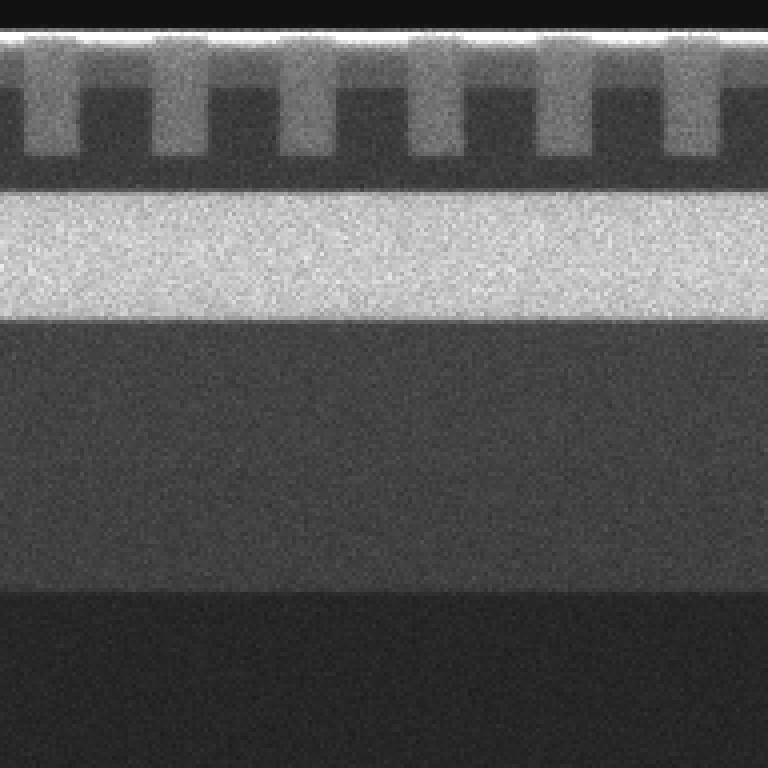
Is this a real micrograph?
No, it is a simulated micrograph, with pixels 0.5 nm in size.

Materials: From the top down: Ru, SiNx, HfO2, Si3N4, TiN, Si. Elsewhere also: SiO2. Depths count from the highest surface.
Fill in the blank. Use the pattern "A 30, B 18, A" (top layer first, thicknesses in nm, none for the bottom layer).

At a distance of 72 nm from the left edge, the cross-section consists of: SiO2 28, SiNx 52, HfO2 64, Si3N4 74, TiN 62, Si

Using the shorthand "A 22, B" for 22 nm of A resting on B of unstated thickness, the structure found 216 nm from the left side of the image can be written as Ru 62, SiNx 18, HfO2 64, Si3N4 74, TiN 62, Si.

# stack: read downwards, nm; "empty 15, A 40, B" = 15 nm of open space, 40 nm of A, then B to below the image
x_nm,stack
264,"SiO2 28, SiNx 52, HfO2 64, Si3N4 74, TiN 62, Si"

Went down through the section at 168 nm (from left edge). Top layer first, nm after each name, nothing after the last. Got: SiO2 28, SiNx 52, HfO2 64, Si3N4 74, TiN 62, Si